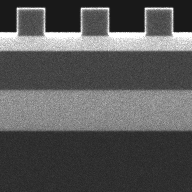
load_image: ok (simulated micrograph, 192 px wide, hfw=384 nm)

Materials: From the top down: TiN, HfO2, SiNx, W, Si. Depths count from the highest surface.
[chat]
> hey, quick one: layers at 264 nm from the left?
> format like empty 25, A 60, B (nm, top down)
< empty 50, HfO2 36, SiNx 78, W 82, Si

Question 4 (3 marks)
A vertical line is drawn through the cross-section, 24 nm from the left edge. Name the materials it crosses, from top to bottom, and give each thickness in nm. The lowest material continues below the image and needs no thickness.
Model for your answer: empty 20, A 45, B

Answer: empty 50, HfO2 36, SiNx 78, W 82, Si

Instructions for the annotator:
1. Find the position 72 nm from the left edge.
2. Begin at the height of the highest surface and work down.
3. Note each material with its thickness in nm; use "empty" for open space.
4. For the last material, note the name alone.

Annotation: TiN 56, HfO2 30, SiNx 78, W 82, Si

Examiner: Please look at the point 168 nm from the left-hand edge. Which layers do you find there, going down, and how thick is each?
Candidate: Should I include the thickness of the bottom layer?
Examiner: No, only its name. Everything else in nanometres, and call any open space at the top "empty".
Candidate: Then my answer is TiN 56, HfO2 30, SiNx 78, W 82, Si